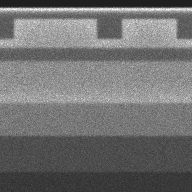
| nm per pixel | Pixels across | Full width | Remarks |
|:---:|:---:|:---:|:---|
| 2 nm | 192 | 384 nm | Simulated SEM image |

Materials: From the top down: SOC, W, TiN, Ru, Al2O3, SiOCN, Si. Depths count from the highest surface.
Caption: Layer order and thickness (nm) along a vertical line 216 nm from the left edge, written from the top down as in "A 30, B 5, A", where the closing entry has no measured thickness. SOC 62, W 18, TiN 26, Ru 84, Al2O3 66, SiOCN 72, Si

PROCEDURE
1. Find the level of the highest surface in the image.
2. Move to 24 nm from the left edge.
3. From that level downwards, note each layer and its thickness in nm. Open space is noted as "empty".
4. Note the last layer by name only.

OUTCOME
SOC 62, W 18, TiN 26, Ru 84, Al2O3 66, SiOCN 72, Si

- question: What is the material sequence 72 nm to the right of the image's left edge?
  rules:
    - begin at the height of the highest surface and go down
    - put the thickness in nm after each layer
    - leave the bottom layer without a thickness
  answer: SOC 22, W 58, TiN 26, Ru 84, Al2O3 66, SiOCN 72, Si